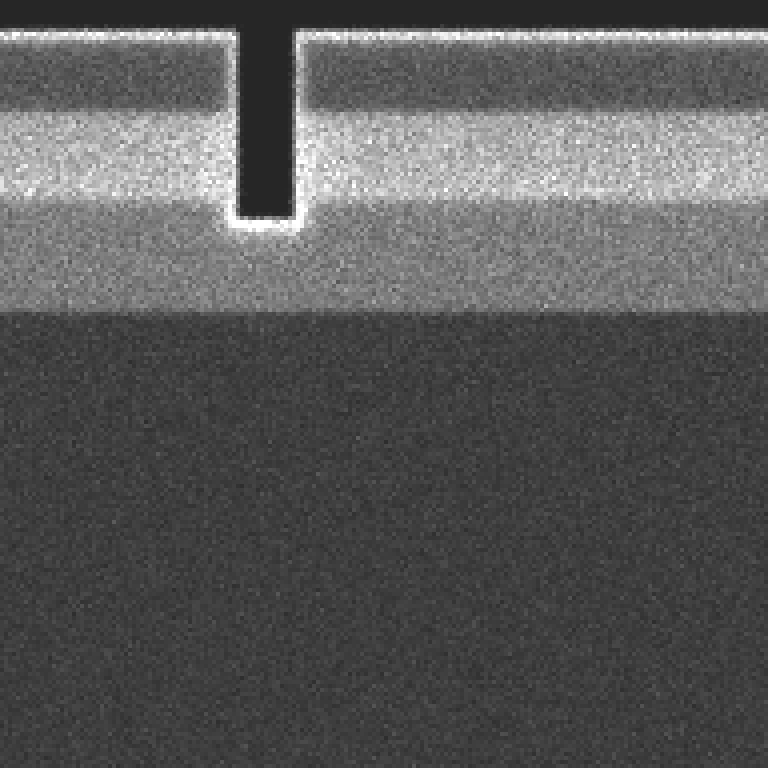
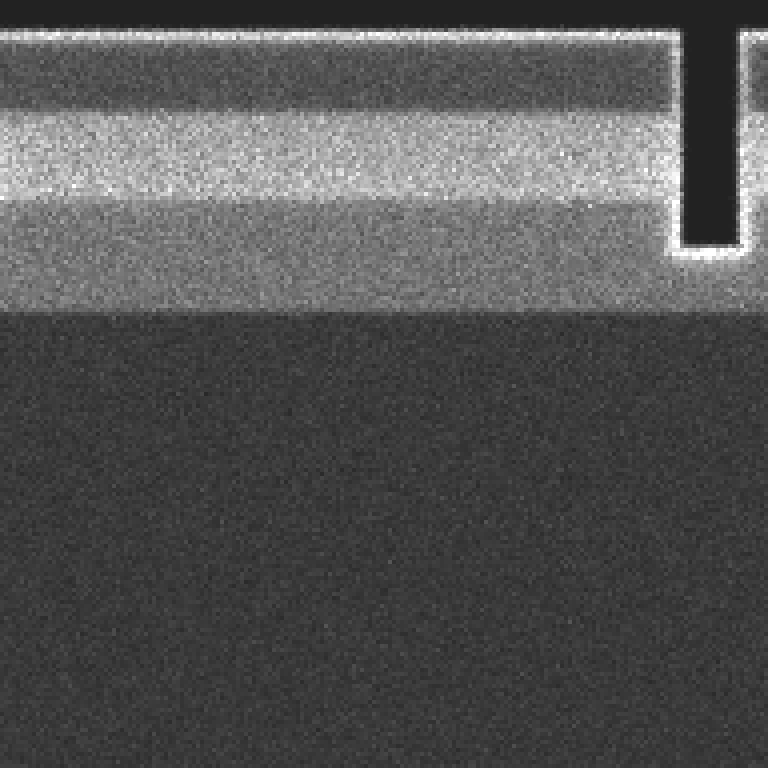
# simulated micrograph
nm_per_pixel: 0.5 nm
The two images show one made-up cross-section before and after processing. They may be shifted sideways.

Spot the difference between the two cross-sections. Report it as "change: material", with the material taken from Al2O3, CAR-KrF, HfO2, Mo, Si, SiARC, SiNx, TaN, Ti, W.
removed: Al2O3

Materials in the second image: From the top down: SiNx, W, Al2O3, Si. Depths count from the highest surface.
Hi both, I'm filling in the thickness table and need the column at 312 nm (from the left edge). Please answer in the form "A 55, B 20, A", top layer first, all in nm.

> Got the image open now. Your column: SiNx 40, W 44, Al2O3 56, Si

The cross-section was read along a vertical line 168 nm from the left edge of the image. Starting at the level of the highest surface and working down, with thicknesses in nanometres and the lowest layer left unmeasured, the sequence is SiNx 40, W 44, Al2O3 56, Si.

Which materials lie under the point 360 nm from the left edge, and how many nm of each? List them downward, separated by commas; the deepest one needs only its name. empty 108, Al2O3 32, Si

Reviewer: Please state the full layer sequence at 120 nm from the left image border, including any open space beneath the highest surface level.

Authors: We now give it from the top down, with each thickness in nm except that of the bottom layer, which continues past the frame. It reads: SiNx 40, W 44, Al2O3 56, Si